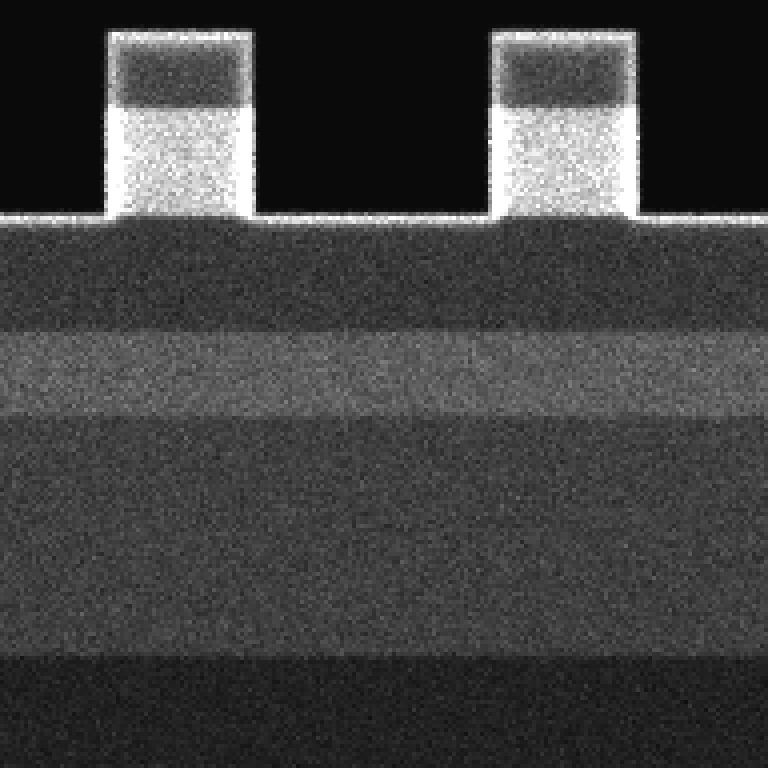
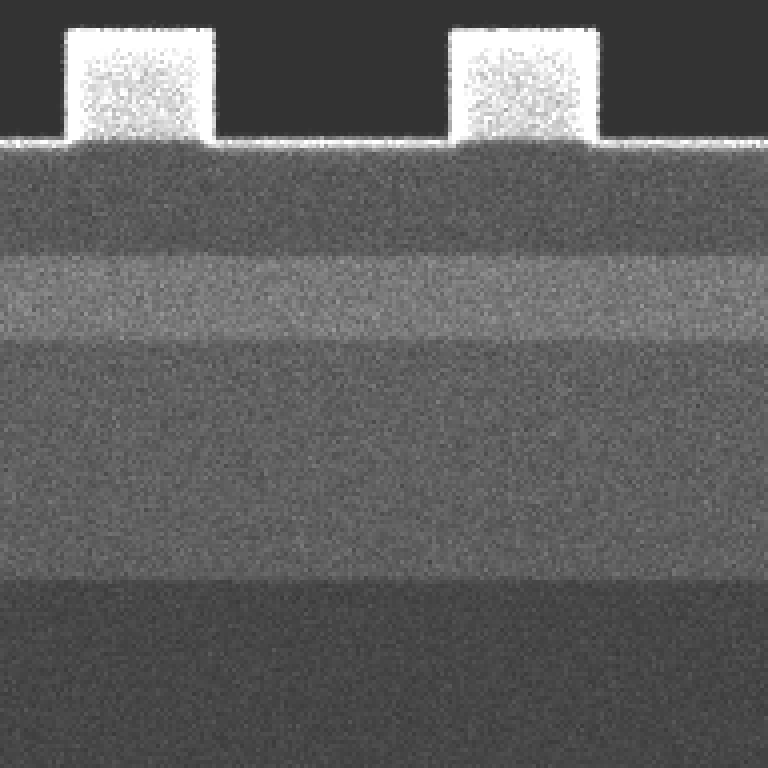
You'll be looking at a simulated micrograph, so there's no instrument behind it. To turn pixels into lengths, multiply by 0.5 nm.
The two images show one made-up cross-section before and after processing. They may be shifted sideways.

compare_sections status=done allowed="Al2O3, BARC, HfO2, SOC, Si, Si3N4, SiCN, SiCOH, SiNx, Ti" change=removed material="SOC"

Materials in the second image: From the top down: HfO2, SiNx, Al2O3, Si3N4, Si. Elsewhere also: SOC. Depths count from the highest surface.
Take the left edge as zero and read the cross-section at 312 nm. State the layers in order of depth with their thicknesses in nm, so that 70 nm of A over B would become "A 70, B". empty 54, SiNx 58, Al2O3 42, Si3N4 120, Si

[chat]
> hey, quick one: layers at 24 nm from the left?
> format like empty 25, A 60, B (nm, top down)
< empty 54, SiNx 58, Al2O3 42, Si3N4 120, Si